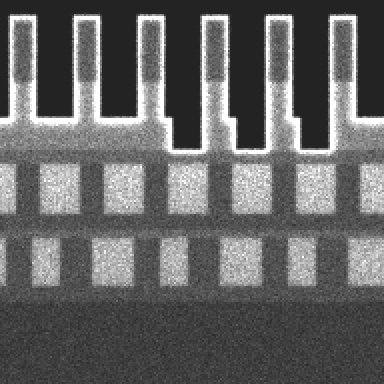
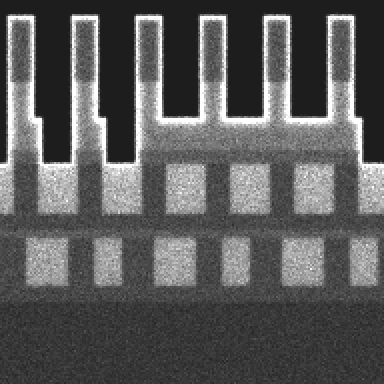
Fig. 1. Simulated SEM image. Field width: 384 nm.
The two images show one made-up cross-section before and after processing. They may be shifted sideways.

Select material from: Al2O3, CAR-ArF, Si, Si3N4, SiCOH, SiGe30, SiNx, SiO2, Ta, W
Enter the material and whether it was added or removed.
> Si3N4 / removed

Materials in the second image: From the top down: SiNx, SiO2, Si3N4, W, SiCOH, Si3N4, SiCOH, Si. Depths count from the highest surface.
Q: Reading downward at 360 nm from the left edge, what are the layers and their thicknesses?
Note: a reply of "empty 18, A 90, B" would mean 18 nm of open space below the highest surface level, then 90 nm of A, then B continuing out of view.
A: empty 102, SiO2 32, Si3N4 14, W 50, SiCOH 16, Si3N4 8, W 48, SiCOH 16, Si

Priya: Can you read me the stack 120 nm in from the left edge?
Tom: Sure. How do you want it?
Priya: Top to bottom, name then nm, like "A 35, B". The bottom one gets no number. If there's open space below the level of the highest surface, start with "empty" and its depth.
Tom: empty 148, W 50, SiCOH 16, Si3N4 8, W 48, SiCOH 16, Si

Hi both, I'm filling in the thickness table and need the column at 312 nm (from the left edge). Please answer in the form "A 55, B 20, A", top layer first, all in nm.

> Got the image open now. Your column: empty 102, SiO2 32, Si3N4 14, W 50, SiCOH 16, Si3N4 8, W 48, SiCOH 16, Si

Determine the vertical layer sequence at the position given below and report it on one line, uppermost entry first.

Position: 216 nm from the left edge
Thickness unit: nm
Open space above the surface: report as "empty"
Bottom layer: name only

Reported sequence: SiNx 66, SiO2 68, Si3N4 14, SiCOH 66, Si3N4 8, SiCOH 64, Si